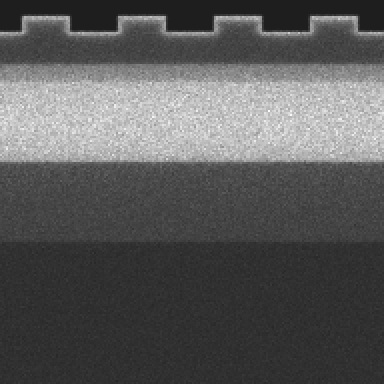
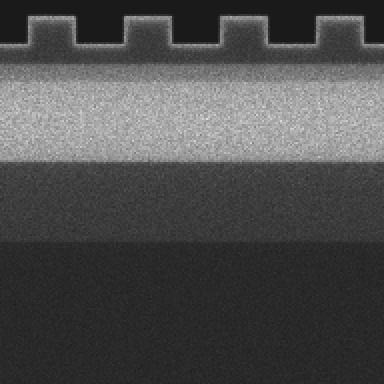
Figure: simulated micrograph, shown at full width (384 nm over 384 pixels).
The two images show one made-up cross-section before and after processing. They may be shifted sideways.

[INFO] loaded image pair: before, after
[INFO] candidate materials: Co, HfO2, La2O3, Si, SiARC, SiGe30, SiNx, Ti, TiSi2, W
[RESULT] removed SiNx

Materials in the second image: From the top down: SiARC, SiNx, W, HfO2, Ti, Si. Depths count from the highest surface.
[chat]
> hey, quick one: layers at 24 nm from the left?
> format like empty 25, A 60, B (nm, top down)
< empty 28, SiNx 20, W 18, HfO2 80, Ti 80, Si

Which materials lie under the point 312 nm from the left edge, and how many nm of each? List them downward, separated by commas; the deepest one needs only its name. empty 28, SiNx 20, W 18, HfO2 80, Ti 80, Si